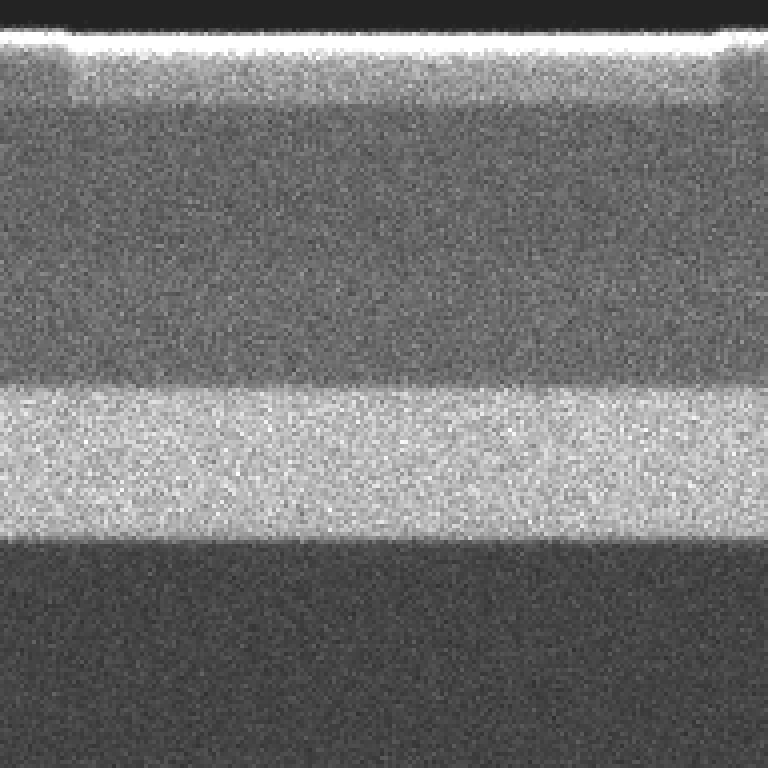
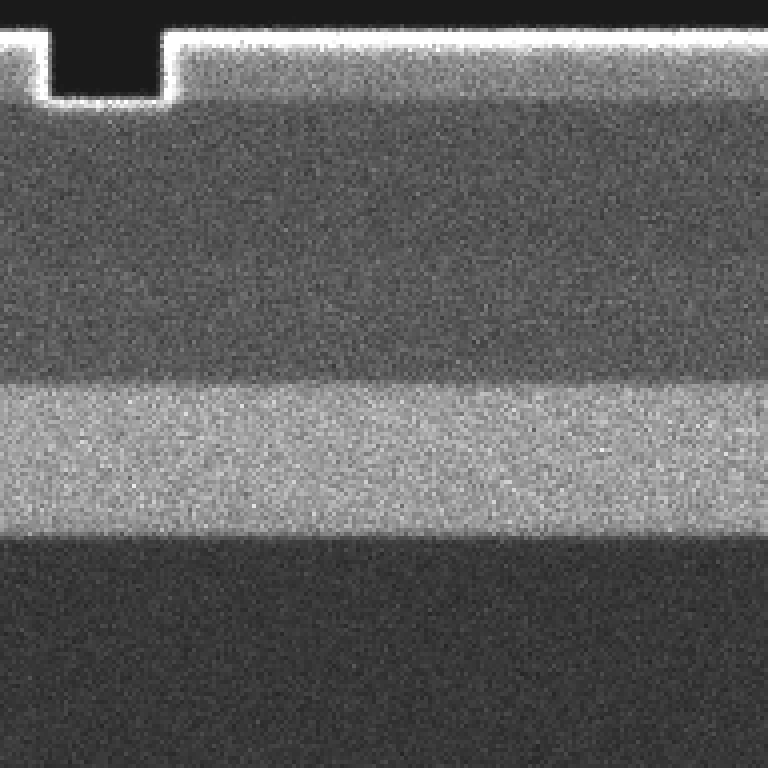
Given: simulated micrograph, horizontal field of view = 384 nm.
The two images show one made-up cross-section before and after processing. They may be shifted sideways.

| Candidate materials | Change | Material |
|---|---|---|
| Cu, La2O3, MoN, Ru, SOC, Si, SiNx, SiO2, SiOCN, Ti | removed | SOC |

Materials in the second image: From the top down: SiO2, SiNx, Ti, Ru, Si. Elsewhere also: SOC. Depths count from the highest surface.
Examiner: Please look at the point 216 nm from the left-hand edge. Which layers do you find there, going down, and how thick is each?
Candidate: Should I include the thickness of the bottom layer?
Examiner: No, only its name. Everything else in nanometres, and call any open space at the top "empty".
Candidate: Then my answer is SiO2 34, SiNx 78, Ti 64, Ru 76, Si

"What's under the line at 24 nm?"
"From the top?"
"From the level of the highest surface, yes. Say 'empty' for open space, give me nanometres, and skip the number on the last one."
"empty 34, SiNx 78, Ti 64, Ru 76, Si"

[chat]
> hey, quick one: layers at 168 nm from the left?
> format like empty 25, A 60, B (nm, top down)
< SiO2 34, SiNx 78, Ti 64, Ru 76, Si